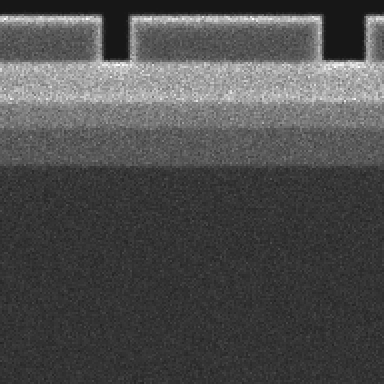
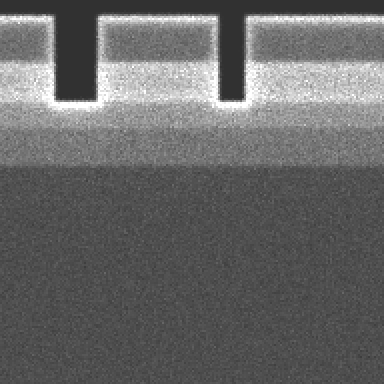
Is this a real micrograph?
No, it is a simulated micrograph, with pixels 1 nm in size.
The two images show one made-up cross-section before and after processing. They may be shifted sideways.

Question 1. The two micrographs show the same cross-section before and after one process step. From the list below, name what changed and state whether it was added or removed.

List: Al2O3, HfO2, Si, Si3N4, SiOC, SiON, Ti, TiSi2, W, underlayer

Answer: W, removed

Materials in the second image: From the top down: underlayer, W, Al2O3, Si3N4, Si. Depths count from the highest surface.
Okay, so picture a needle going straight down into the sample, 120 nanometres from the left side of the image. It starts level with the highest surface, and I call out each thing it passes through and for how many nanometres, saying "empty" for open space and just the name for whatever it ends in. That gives underlayer 46, W 40, Al2O3 26, Si3N4 38, Si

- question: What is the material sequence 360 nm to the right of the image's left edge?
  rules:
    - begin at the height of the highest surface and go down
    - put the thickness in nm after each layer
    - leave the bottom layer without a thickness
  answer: underlayer 46, W 40, Al2O3 26, Si3N4 38, Si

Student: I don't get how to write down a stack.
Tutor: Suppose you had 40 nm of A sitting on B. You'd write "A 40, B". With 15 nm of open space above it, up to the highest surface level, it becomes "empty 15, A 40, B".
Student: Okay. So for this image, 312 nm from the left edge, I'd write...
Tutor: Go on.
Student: underlayer 46, W 40, Al2O3 26, Si3N4 38, Si